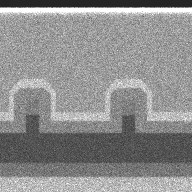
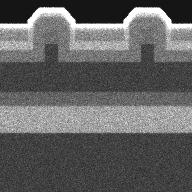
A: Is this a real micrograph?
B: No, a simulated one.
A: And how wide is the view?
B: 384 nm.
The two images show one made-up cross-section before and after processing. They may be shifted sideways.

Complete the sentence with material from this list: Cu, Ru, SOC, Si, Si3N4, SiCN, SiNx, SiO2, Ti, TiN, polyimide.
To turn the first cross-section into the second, SOC must be removed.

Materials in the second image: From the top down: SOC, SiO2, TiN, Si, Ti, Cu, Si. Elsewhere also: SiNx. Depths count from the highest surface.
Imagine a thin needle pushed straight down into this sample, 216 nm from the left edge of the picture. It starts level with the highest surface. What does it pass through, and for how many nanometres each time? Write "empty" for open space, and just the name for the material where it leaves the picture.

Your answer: empty 32, SOC 34, SiO2 18, TiN 24, Si 60, Ti 28, Cu 54, Si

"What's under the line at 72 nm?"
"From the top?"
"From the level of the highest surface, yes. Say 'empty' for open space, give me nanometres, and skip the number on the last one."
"empty 6, SiO2 18, TiN 84, Si 60, Ti 28, Cu 54, Si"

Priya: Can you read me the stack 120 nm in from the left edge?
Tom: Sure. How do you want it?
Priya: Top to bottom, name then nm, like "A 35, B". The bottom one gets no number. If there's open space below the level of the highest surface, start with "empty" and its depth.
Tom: SiO2 18, TiN 90, Si 60, Ti 28, Cu 54, Si